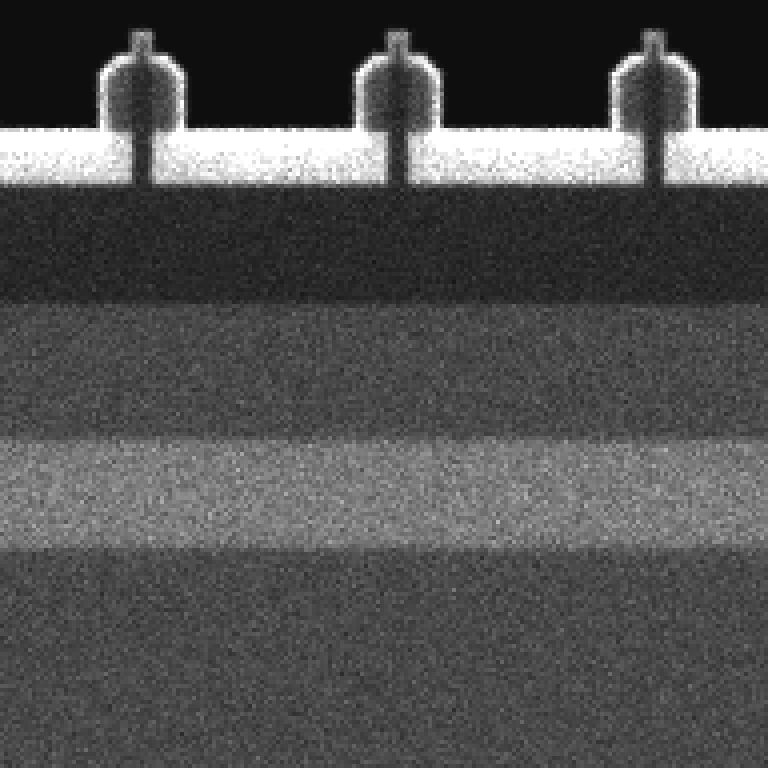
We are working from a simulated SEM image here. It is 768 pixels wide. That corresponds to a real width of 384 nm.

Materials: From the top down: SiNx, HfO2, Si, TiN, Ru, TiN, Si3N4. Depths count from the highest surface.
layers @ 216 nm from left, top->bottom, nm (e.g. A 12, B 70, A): empty 18, SiNx 32, HfO2 26, Si 60, TiN 68, Ru 54, TiN 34, Si3N4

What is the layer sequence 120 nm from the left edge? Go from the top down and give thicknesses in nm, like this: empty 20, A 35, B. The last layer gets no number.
empty 50, HfO2 26, Si 60, TiN 68, Ru 54, TiN 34, Si3N4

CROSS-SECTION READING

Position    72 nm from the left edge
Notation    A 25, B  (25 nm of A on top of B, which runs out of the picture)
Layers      Si 136, TiN 68, Ru 54, TiN 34, Si3N4